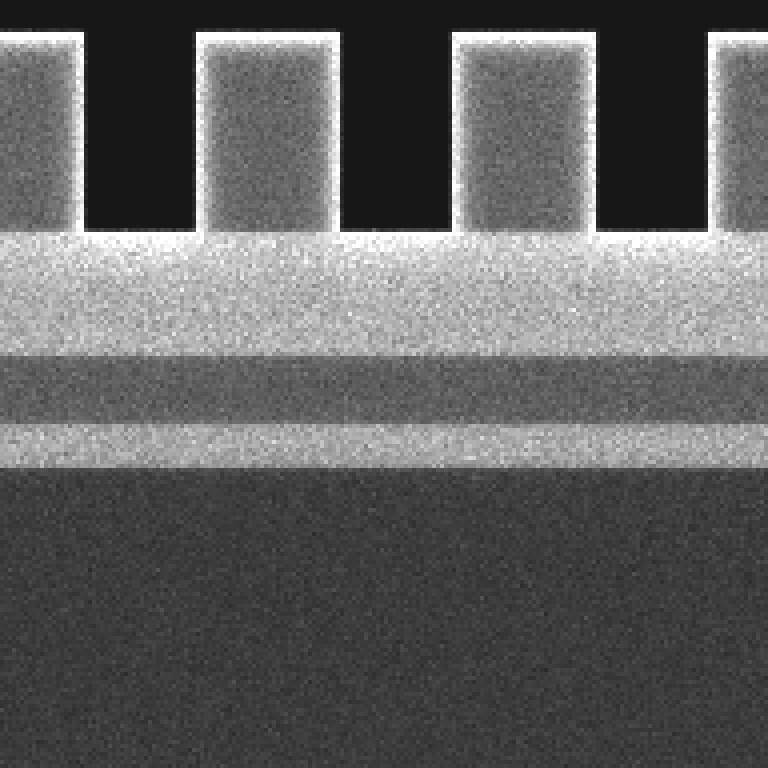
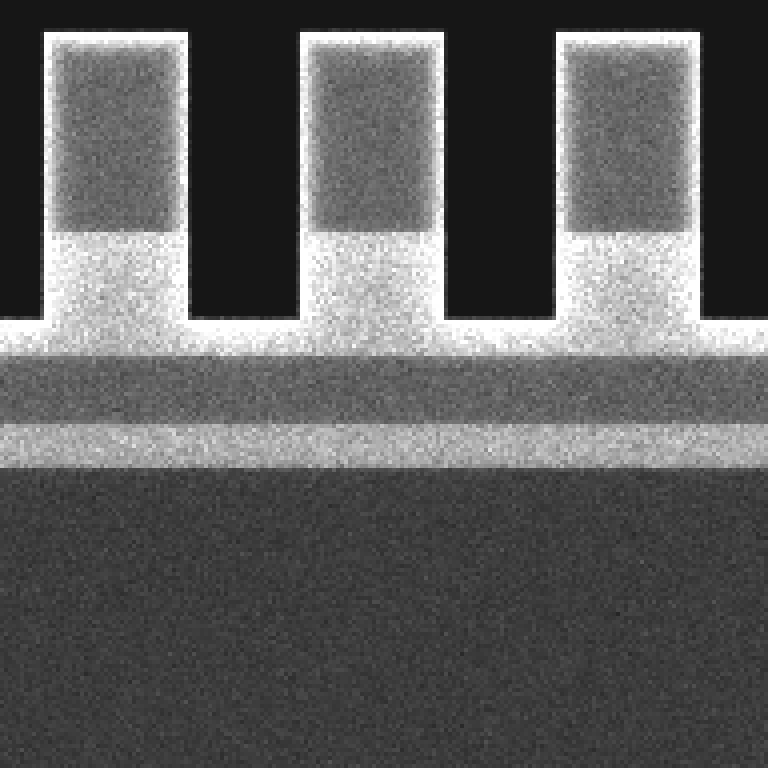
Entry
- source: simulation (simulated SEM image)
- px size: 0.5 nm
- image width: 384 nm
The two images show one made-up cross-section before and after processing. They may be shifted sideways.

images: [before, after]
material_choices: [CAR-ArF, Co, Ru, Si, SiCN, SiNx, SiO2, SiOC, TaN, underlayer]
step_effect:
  removed: Ru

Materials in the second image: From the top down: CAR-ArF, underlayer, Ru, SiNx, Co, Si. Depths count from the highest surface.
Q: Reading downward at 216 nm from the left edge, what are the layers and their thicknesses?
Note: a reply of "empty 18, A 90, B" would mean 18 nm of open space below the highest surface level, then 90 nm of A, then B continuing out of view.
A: CAR-ArF 76, underlayer 24, Ru 62, SiNx 34, Co 22, Si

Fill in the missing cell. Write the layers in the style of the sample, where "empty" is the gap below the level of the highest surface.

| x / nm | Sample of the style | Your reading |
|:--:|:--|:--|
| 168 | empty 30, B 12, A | CAR-ArF 76, underlayer 24, Ru 62, SiNx 34, Co 22, Si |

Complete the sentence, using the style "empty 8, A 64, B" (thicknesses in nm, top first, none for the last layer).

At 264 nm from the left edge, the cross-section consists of empty 144, Ru 18, SiNx 34, Co 22, Si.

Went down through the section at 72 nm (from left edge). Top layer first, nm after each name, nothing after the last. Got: CAR-ArF 76, underlayer 24, Ru 62, SiNx 34, Co 22, Si